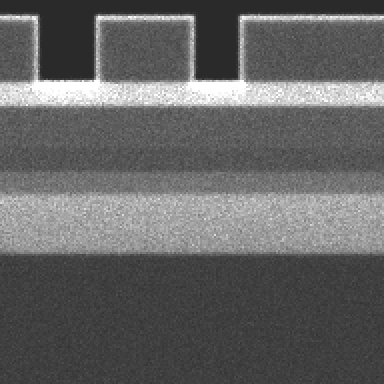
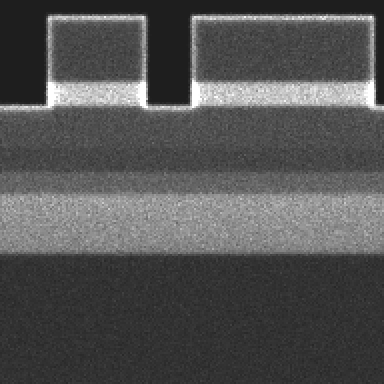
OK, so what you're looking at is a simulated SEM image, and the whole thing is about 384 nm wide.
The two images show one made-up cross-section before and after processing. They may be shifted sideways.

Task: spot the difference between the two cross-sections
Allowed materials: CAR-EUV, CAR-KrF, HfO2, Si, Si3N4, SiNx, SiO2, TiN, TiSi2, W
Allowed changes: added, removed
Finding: removed HfO2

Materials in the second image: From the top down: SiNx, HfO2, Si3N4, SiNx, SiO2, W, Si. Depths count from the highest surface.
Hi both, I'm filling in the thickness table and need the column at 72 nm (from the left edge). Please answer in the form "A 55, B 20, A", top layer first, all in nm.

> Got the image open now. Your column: SiNx 66, HfO2 24, Si3N4 42, SiNx 24, SiO2 22, W 60, Si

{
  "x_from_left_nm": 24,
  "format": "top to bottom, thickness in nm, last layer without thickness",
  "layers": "empty 90, Si3N4 42, SiNx 24, SiO2 22, W 60, Si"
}